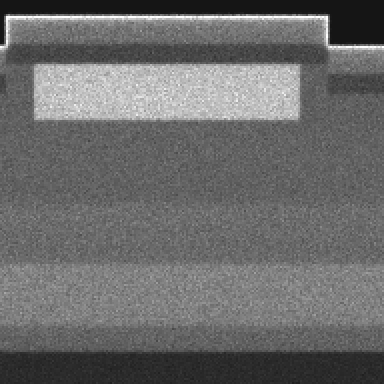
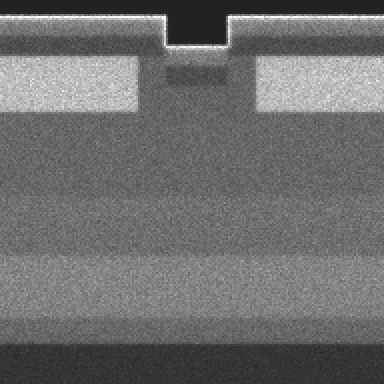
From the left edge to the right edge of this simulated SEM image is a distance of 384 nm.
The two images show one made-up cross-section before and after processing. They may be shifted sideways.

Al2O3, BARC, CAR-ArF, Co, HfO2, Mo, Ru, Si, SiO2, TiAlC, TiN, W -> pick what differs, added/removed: Ru removed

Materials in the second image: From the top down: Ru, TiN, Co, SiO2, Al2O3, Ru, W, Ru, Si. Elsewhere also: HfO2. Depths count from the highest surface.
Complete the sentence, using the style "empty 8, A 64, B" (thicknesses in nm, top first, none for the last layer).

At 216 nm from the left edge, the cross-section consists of empty 30, Ru 20, TiN 20, Co 10, SiO2 28, Al2O3 72, Ru 60, W 62, Ru 26, Si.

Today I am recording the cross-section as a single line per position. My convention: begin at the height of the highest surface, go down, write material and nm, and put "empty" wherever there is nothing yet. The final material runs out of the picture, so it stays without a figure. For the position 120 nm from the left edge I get Ru 20, TiN 20, HfO2 56, Al2O3 84, Ru 60, W 62, Ru 26, Si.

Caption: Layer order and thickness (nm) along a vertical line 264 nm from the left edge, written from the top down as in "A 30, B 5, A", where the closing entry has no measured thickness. Ru 20, TiN 20, HfO2 56, Al2O3 84, Ru 60, W 62, Ru 26, Si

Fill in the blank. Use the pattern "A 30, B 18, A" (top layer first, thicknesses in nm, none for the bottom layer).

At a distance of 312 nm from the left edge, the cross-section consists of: Ru 20, TiN 20, HfO2 56, Al2O3 84, Ru 60, W 62, Ru 26, Si